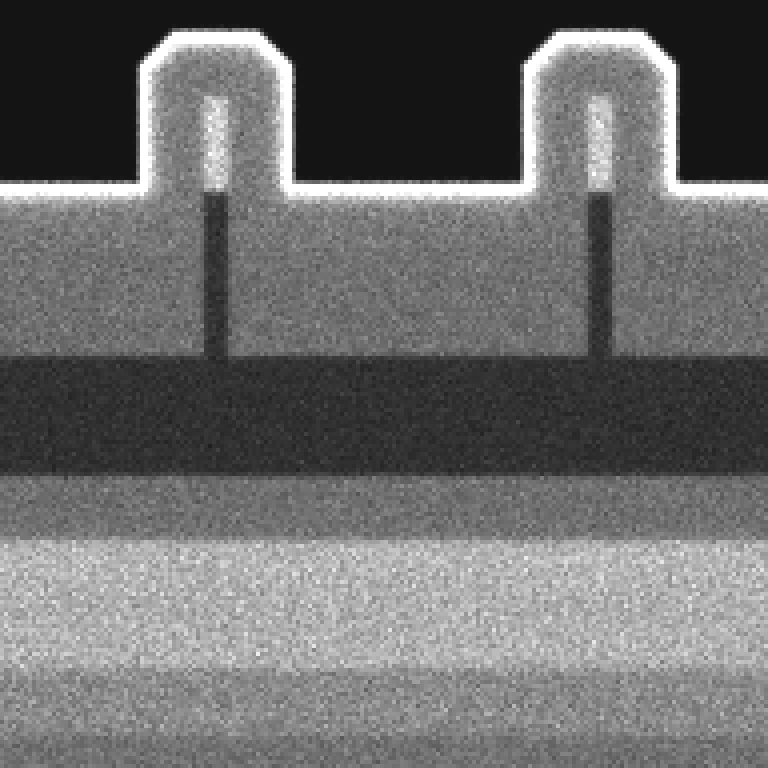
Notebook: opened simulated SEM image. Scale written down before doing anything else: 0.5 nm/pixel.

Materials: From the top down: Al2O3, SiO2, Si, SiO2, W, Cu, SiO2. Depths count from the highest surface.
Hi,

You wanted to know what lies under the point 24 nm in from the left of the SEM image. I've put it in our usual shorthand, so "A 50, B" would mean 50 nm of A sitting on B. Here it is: empty 76, Al2O3 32, SiO2 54, Si 60, SiO2 32, W 64, Cu 34, SiO2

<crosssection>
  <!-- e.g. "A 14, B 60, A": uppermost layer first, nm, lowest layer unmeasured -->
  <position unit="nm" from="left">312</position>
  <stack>Al2O3 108, SiO2 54, Si 60, SiO2 32, W 64, Cu 34, SiO2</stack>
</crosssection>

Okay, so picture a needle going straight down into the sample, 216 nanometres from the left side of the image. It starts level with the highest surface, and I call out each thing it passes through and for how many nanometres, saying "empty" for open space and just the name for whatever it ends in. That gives empty 76, Al2O3 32, SiO2 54, Si 60, SiO2 32, W 64, Cu 34, SiO2